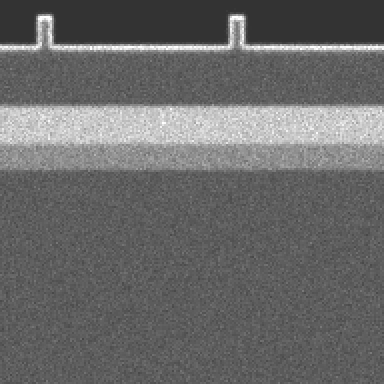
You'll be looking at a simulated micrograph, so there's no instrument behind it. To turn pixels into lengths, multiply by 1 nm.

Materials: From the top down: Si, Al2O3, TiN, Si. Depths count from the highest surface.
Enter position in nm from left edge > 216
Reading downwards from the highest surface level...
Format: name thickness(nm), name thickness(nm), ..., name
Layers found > empty 30, Si 60, Al2O3 38, TiN 26, Si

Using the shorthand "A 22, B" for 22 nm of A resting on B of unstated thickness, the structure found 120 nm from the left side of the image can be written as empty 30, Si 60, Al2O3 38, TiN 26, Si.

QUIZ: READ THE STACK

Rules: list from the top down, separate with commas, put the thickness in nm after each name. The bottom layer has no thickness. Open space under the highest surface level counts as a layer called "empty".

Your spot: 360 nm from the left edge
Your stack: empty 30, Si 60, Al2O3 38, TiN 26, Si